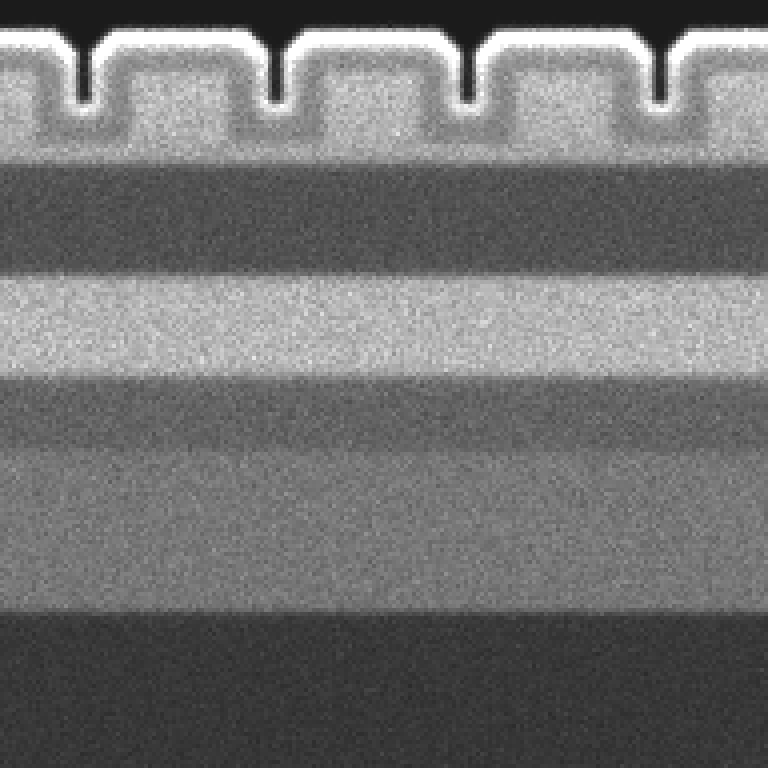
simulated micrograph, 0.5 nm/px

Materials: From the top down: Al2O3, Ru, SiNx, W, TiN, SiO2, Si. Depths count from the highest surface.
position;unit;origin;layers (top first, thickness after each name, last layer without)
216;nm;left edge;Al2O3 56, Ru 10, SiNx 56, W 50, TiN 38, SiO2 80, Si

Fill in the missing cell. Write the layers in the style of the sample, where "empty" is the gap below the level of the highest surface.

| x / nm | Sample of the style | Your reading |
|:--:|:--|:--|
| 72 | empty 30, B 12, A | Al2O3 20, Ru 46, SiNx 56, W 50, TiN 38, SiO2 80, Si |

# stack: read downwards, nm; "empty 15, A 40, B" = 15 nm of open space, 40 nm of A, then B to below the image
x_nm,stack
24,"Al2O3 56, Ru 10, SiNx 56, W 50, TiN 38, SiO2 80, Si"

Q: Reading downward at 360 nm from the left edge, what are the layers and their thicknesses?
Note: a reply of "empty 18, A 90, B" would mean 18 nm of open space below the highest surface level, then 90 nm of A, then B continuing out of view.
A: Al2O3 20, Ru 46, SiNx 56, W 50, TiN 38, SiO2 80, Si